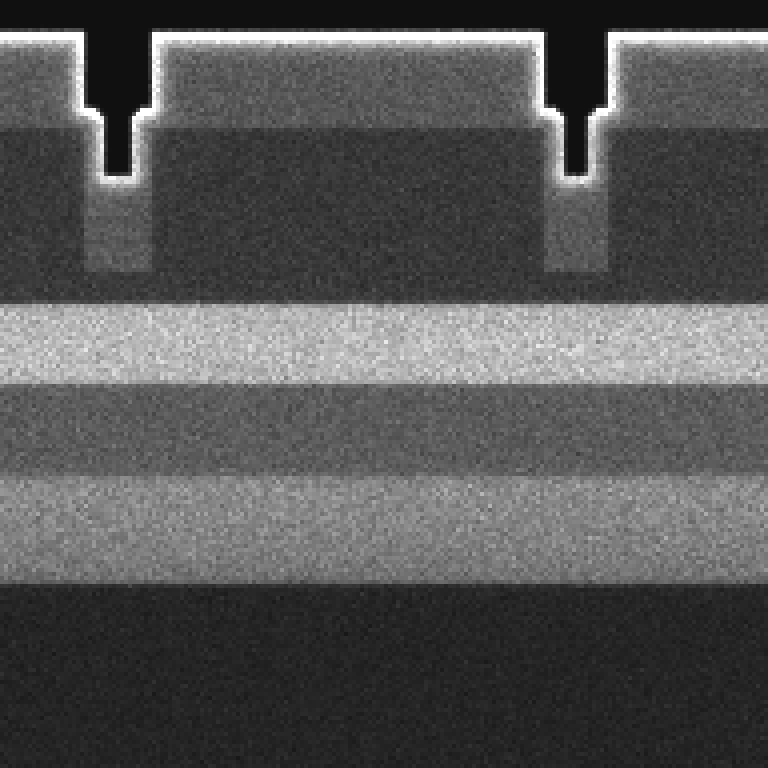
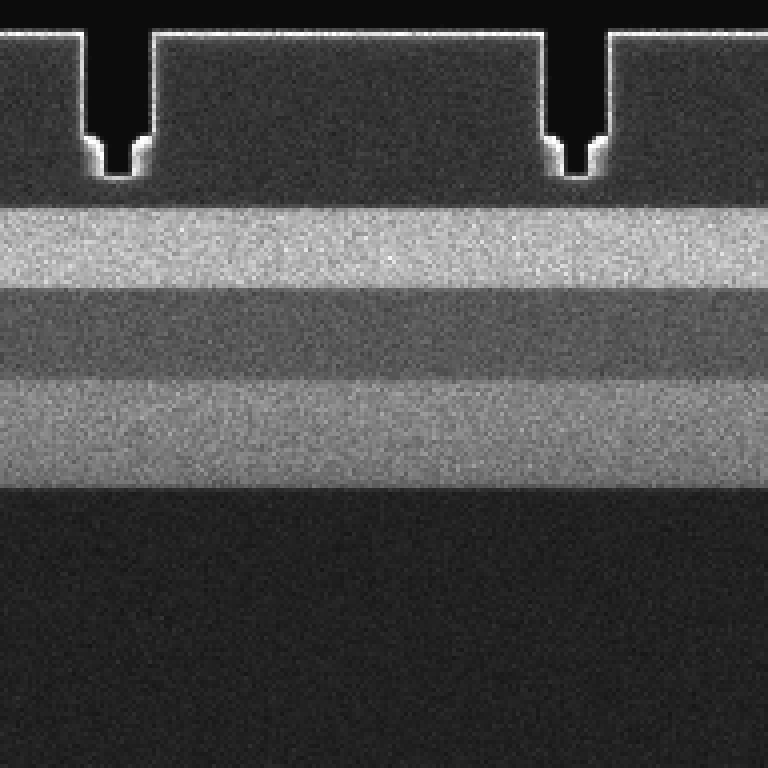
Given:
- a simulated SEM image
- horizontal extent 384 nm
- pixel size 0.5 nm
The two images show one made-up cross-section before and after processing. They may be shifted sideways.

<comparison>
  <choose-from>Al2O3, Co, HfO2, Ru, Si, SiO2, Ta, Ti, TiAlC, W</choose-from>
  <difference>SiO2 removed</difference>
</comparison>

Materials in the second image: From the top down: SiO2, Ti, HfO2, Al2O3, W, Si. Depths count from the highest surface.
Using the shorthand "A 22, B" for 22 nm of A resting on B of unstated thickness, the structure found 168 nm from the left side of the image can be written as Ti 88, HfO2 40, Al2O3 46, W 54, Si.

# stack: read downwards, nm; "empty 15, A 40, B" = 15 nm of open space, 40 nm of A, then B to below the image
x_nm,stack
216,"Ti 88, HfO2 40, Al2O3 46, W 54, Si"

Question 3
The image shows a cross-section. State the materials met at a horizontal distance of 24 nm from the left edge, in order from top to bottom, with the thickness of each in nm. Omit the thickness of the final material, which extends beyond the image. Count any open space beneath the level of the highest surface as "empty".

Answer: Ti 88, HfO2 40, Al2O3 46, W 54, Si